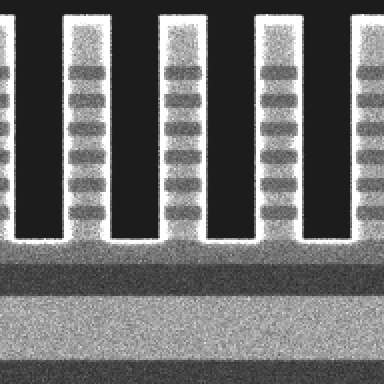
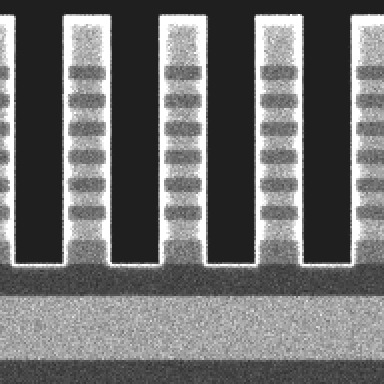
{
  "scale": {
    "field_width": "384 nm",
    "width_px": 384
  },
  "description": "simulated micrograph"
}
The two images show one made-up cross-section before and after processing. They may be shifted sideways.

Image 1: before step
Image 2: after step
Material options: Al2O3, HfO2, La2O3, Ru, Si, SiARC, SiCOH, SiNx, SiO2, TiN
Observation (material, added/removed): TiN, removed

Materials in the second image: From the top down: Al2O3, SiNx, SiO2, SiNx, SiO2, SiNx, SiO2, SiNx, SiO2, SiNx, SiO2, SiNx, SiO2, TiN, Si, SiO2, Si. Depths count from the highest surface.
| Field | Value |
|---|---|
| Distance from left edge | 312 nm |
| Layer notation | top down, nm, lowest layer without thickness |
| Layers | empty 248, Si 32, SiO2 64, Si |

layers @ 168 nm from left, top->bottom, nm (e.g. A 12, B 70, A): Al2O3 50, SiNx 14, SiO2 14, SiNx 14, SiO2 14, SiNx 14, SiO2 14, SiNx 14, SiO2 14, SiNx 14, SiO2 14, SiNx 14, SiO2 20, TiN 24, Si 32, SiO2 64, Si